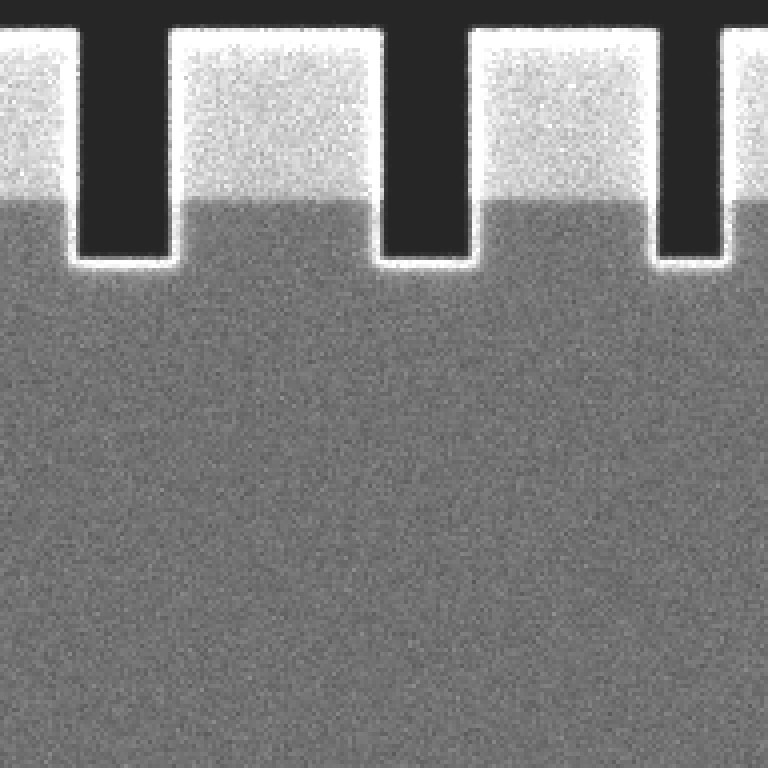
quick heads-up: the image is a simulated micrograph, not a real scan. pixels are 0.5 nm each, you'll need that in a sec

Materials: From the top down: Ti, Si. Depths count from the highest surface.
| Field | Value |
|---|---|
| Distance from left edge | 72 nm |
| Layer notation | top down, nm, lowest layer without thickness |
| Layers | empty 114, Si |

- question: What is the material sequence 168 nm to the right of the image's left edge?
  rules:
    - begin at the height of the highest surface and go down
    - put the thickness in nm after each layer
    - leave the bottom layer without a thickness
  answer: Ti 84, Si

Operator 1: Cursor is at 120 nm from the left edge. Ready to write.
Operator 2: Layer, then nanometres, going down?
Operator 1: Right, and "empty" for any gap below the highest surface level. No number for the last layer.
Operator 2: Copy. Ti 84, Si